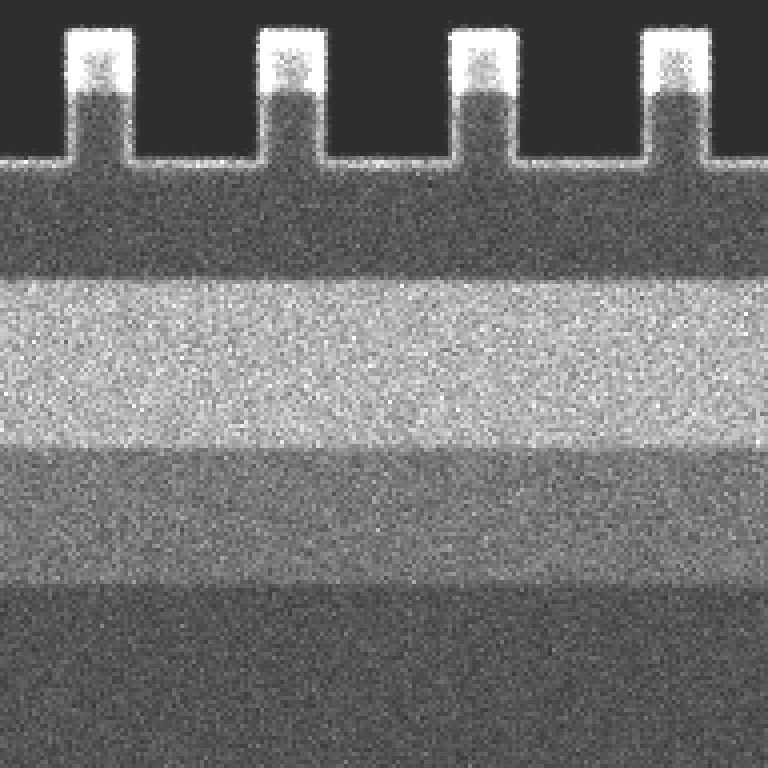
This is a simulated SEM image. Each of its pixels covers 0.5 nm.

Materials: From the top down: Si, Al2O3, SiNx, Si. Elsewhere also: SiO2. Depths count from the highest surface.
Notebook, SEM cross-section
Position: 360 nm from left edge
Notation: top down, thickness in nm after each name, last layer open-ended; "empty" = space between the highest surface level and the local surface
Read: empty 64, Si 60, Al2O3 84, SiNx 68, Si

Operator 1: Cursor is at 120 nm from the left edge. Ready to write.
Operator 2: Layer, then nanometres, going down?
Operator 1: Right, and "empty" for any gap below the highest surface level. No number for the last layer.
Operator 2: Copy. empty 64, Si 60, Al2O3 84, SiNx 68, Si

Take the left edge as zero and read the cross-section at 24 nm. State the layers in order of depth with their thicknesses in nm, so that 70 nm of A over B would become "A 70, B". empty 64, Si 60, Al2O3 84, SiNx 68, Si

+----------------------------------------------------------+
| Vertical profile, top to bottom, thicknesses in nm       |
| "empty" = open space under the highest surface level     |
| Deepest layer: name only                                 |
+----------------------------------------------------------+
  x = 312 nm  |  empty 64, Si 60, Al2O3 84, SiNx 68, Si